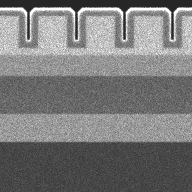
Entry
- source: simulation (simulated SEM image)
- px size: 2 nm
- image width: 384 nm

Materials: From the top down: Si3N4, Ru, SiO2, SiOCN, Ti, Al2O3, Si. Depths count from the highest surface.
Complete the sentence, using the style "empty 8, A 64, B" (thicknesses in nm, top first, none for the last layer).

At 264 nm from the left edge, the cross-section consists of Si3N4 80, Ru 14, SiO2 42, SiOCN 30, Ti 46, Al2O3 56, Si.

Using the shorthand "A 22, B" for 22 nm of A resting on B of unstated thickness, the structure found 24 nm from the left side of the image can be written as Si3N4 16, Ru 78, SiO2 42, SiOCN 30, Ti 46, Al2O3 56, Si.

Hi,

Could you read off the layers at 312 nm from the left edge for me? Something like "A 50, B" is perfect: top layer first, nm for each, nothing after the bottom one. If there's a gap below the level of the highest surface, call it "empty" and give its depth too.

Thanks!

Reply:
Si3N4 16, Ru 78, SiO2 42, SiOCN 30, Ti 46, Al2O3 56, Si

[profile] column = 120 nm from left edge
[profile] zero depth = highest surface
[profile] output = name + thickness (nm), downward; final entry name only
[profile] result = Si3N4 16, Ru 78, SiO2 42, SiOCN 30, Ti 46, Al2O3 56, Si